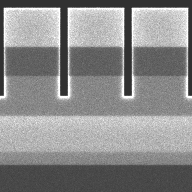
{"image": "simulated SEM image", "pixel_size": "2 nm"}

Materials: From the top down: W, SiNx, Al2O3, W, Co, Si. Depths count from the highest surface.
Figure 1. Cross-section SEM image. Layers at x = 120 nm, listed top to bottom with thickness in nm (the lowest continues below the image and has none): empty 176, Al2O3 40, W 72, Co 26, Si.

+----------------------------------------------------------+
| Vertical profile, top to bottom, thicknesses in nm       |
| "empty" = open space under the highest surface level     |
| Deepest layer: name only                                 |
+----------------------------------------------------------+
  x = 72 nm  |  W 78, SiNx 58, Al2O3 80, W 72, Co 26, Si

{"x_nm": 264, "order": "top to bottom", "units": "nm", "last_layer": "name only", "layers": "W 78, SiNx 58, Al2O3 80, W 72, Co 26, Si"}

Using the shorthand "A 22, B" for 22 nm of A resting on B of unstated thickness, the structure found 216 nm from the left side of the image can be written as W 78, SiNx 58, Al2O3 80, W 72, Co 26, Si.